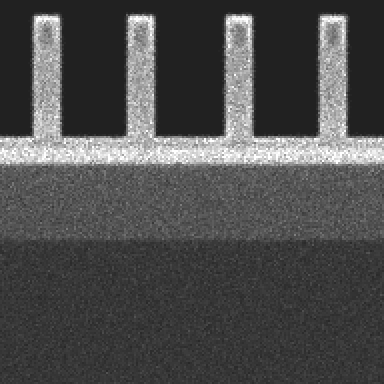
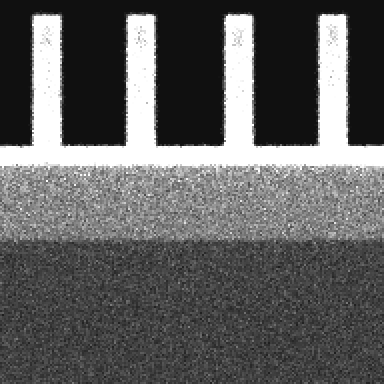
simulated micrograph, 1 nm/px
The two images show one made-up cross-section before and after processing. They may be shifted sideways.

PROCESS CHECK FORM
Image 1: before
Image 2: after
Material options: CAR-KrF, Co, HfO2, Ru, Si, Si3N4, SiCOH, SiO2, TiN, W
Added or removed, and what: removed, Co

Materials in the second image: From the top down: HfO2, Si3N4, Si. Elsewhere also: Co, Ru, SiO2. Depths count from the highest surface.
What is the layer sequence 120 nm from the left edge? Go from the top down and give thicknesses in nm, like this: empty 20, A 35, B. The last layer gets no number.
empty 132, HfO2 16, Si3N4 76, Si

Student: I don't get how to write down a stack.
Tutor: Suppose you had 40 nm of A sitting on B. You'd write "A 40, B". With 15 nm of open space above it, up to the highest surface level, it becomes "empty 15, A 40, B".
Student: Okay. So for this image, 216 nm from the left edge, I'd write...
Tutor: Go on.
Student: empty 132, HfO2 16, Si3N4 76, Si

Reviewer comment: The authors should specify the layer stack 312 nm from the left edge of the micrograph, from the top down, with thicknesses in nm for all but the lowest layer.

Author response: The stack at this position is empty 132, HfO2 16, Si3N4 76, Si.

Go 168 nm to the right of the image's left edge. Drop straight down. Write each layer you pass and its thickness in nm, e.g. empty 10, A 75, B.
empty 132, HfO2 16, Si3N4 76, Si